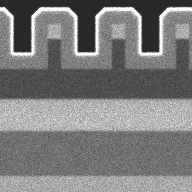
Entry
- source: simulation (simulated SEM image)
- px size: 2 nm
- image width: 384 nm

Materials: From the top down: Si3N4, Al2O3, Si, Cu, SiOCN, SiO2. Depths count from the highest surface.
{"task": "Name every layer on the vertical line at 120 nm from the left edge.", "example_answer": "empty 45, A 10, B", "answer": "Si3N4 32, Al2O3 30, Si 120, Cu 64, SiOCN 90, SiO2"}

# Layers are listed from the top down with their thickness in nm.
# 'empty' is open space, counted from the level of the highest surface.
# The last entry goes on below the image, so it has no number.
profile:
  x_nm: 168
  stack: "empty 90, Si3N4 32, Si 60, Cu 64, SiOCN 90, SiO2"